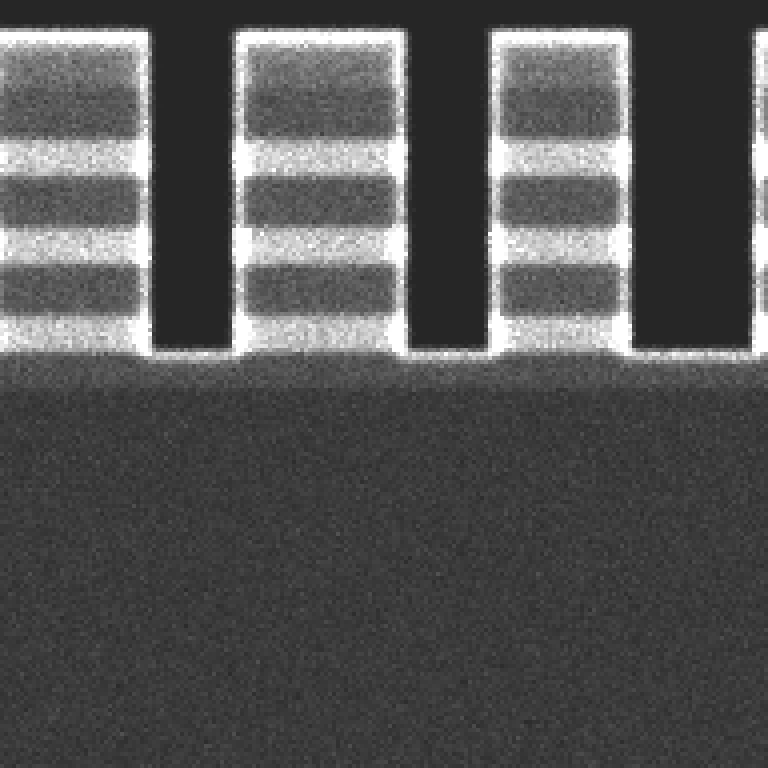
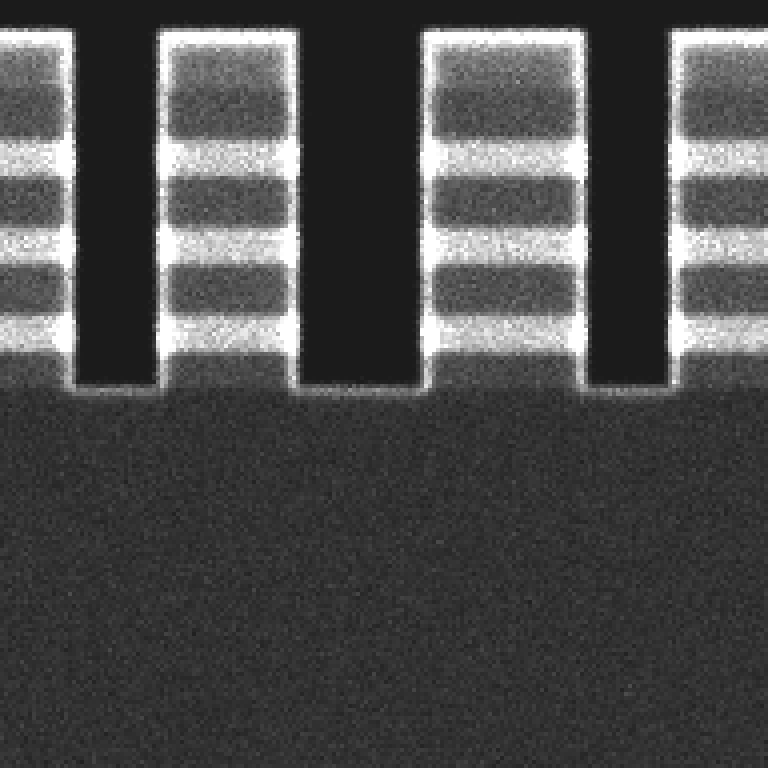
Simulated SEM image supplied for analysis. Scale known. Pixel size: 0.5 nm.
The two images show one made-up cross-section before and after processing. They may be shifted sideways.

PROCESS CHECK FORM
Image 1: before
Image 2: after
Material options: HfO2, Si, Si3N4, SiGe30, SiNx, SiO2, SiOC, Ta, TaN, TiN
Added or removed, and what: removed, SiNx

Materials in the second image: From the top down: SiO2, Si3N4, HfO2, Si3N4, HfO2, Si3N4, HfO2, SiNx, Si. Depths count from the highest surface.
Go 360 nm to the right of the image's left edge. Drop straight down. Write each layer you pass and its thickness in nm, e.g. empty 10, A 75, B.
SiO2 28, Si3N4 26, HfO2 18, Si3N4 26, HfO2 18, Si3N4 26, HfO2 18, SiNx 18, Si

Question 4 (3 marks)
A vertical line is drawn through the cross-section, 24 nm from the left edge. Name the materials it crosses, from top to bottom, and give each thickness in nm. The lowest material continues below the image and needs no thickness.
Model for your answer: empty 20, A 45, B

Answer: SiO2 28, Si3N4 26, HfO2 18, Si3N4 26, HfO2 18, Si3N4 26, HfO2 18, SiNx 18, Si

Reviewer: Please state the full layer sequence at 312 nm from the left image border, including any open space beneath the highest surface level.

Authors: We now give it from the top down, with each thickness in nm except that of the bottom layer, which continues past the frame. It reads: empty 178, Si